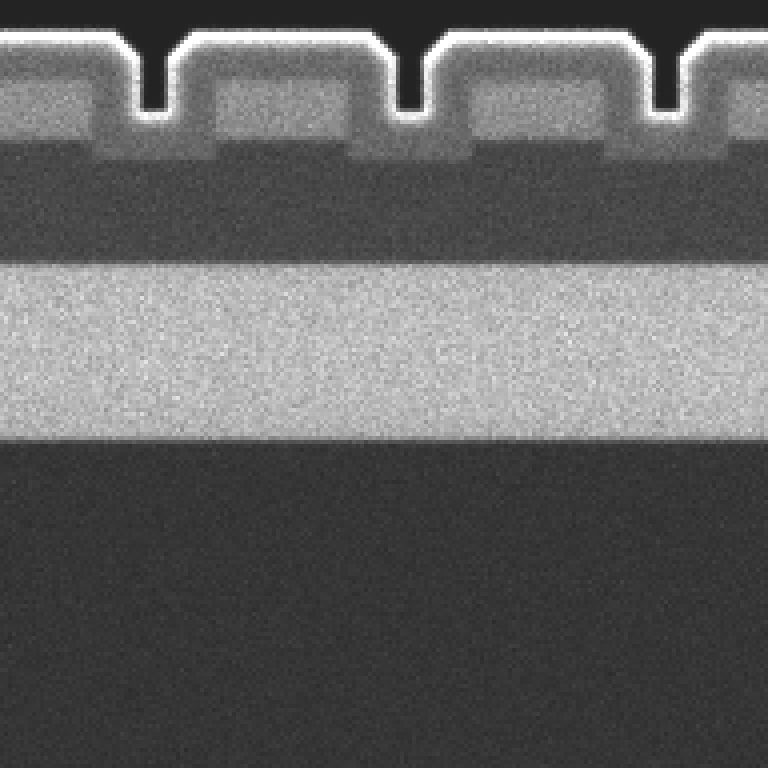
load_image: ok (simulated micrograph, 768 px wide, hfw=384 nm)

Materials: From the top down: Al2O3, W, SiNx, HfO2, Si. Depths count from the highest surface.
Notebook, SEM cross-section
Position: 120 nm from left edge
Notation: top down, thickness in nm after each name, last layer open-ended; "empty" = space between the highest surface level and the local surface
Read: Al2O3 24, W 30, SiNx 62, HfO2 88, Si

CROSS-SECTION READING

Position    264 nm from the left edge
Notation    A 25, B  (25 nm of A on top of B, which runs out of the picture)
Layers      Al2O3 24, W 30, SiNx 62, HfO2 88, Si